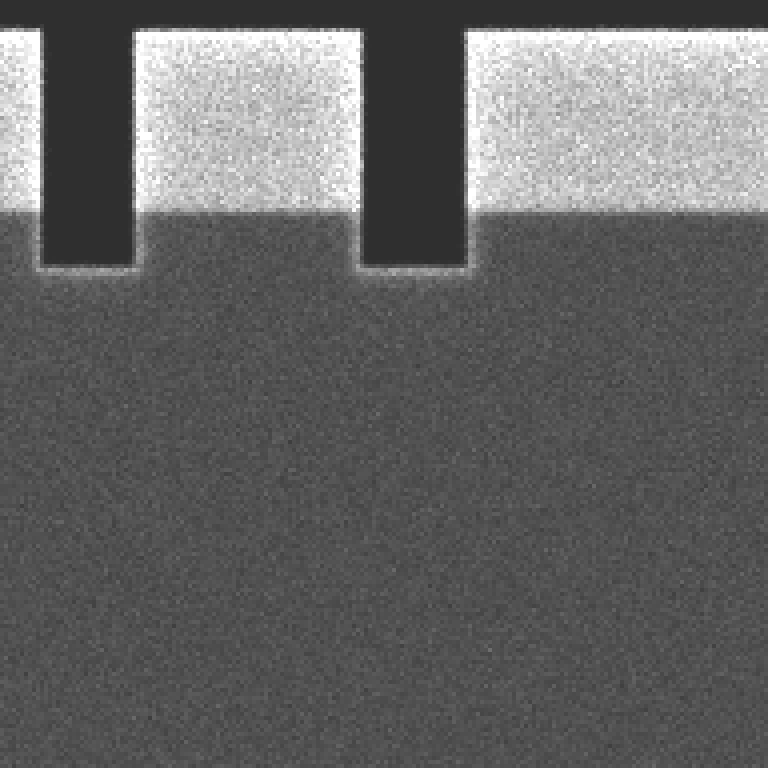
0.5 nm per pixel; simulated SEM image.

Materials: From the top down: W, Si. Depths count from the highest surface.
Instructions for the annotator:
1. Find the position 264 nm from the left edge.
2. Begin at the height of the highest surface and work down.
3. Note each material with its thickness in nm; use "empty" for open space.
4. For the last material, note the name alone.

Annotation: W 90, Si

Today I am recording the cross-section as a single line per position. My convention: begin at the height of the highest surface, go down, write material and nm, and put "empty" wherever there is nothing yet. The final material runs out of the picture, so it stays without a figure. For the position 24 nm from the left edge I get empty 118, Si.